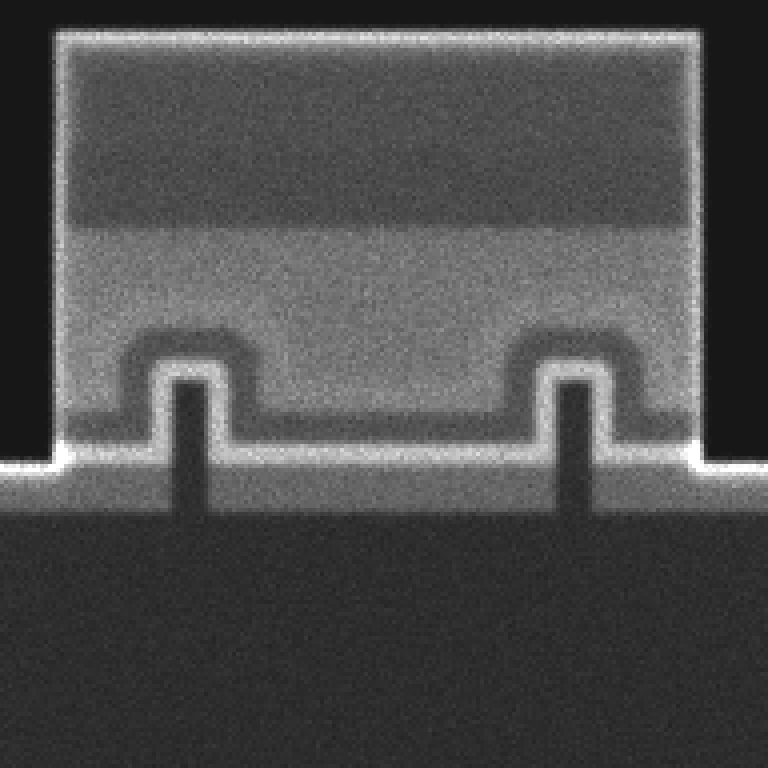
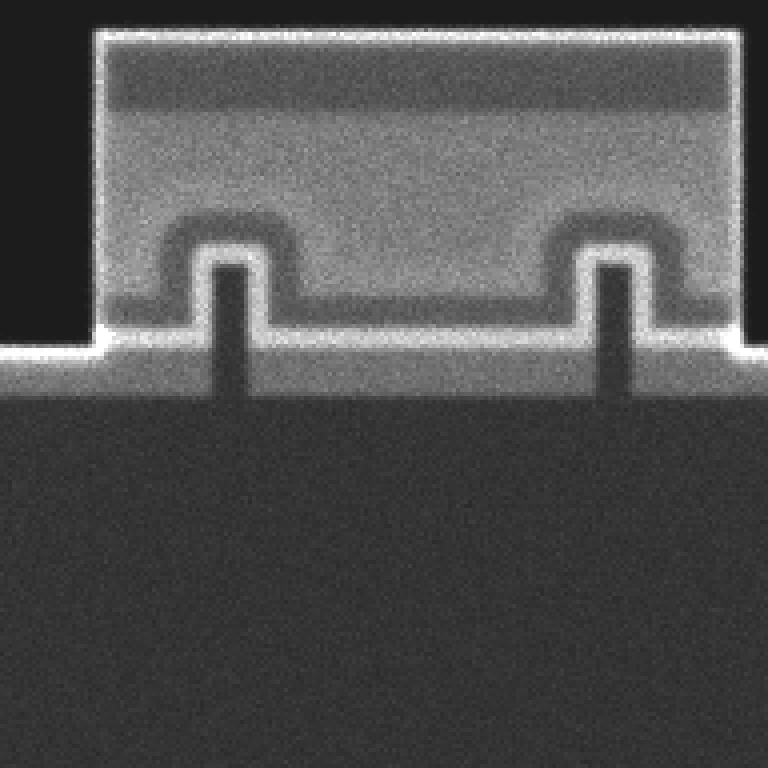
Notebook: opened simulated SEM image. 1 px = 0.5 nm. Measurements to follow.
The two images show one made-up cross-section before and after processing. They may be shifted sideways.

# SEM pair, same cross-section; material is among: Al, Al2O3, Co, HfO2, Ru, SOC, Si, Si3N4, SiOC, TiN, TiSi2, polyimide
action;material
removed;SOC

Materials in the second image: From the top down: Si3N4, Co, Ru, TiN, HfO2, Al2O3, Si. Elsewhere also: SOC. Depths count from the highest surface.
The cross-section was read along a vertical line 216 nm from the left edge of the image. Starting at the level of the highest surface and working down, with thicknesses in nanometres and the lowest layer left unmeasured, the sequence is Si3N4 40, Co 76, Ru 16, TiN 16, HfO2 10, Al2O3 24, Si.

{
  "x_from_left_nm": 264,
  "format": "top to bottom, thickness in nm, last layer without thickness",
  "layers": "Si3N4 40, Co 46, Ru 46, TiN 16, HfO2 10, Al2O3 24, Si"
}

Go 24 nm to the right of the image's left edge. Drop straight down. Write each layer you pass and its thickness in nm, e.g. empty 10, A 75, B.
empty 158, Al2O3 24, Si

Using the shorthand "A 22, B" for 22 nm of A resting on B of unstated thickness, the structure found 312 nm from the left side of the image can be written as Si3N4 40, Co 34, Ru 16, TiN 16, HfO2 10, Si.